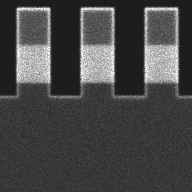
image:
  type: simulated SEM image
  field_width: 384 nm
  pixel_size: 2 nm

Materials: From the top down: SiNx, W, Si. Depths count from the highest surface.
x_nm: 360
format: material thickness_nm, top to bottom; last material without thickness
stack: empty 176, Si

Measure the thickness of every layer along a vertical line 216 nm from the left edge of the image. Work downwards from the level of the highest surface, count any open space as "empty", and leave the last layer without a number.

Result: SiNx 74, W 76, Si